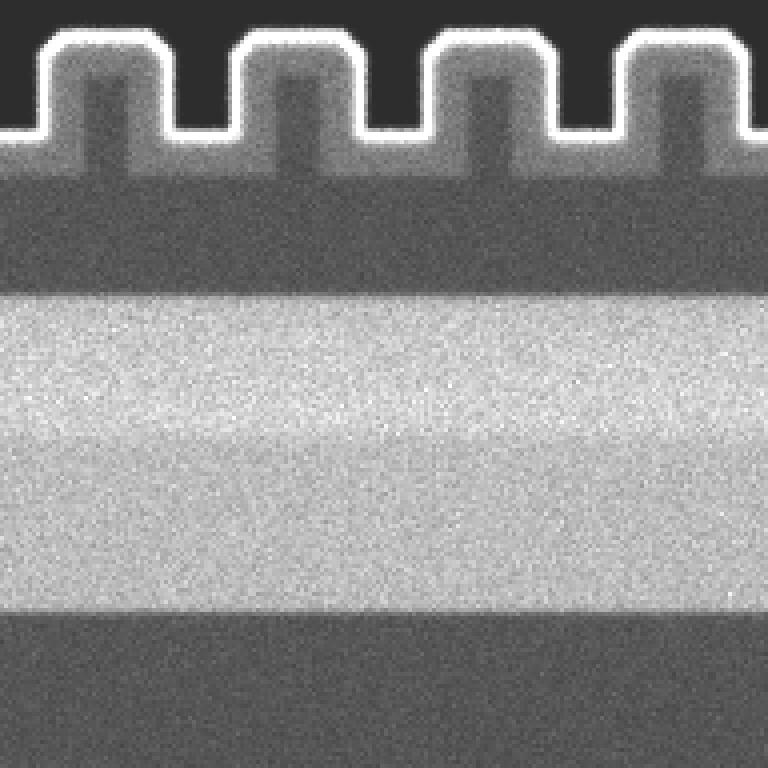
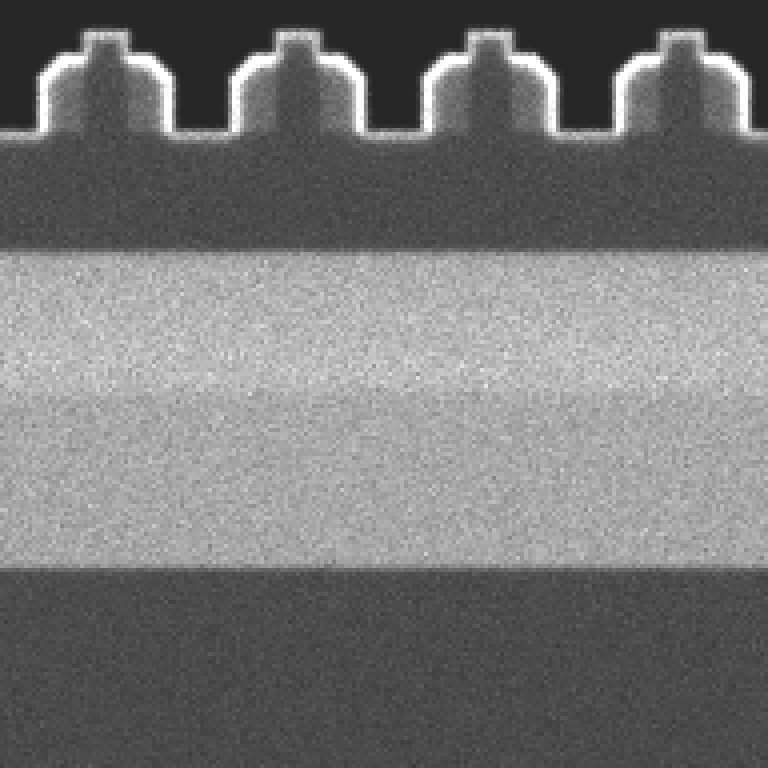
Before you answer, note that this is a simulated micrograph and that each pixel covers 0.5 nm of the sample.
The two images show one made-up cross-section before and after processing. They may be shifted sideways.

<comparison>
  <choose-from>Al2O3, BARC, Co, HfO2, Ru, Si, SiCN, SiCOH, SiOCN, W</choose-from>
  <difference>SiOCN removed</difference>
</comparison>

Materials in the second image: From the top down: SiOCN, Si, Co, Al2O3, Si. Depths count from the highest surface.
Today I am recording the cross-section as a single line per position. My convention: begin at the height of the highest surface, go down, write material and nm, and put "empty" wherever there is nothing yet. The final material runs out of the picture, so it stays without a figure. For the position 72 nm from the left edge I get empty 12, SiOCN 38, Si 60, Co 70, Al2O3 88, Si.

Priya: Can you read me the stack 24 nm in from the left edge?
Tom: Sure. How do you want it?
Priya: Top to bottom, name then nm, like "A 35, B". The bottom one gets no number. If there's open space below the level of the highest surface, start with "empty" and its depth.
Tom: empty 18, SiOCN 32, Si 60, Co 70, Al2O3 88, Si